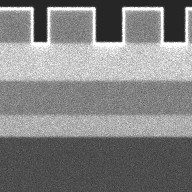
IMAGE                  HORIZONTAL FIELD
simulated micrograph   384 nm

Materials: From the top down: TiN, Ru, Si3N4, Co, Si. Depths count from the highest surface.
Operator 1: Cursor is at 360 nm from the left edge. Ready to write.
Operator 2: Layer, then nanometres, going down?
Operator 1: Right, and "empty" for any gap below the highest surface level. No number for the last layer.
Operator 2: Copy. empty 70, Ru 76, Si3N4 68, Co 44, Si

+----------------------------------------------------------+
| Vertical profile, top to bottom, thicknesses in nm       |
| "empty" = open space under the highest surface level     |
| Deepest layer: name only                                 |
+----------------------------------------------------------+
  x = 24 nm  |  TiN 70, Ru 76, Si3N4 68, Co 44, Si